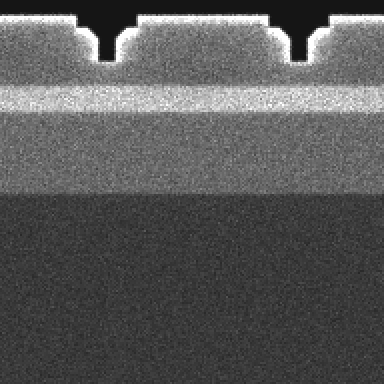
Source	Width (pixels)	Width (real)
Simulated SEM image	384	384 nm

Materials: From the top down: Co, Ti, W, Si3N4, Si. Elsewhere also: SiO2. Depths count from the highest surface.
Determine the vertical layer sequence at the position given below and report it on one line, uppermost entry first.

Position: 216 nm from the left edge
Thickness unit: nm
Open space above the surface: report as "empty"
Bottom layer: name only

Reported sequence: Co 8, Ti 62, W 26, Si3N4 82, Si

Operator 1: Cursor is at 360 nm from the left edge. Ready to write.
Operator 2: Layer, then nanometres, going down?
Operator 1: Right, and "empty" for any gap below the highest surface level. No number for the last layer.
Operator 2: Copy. Co 8, Ti 62, W 26, Si3N4 82, Si